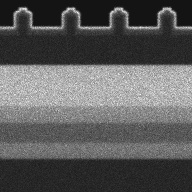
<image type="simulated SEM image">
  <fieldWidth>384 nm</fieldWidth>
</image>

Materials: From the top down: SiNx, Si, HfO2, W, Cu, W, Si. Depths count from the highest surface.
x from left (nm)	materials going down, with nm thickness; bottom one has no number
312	empty 38, SiNx 16, Si 60, HfO2 82, W 34, Cu 40, W 32, Si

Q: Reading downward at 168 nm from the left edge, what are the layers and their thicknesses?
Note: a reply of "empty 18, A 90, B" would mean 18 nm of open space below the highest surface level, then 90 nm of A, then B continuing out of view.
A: empty 38, SiNx 16, Si 60, HfO2 82, W 34, Cu 40, W 32, Si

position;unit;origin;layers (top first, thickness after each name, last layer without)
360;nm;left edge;empty 38, SiNx 16, Si 60, HfO2 82, W 34, Cu 40, W 32, Si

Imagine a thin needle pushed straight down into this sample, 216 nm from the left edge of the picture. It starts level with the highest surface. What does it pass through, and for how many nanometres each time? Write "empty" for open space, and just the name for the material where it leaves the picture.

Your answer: empty 38, SiNx 16, Si 60, HfO2 82, W 34, Cu 40, W 32, Si